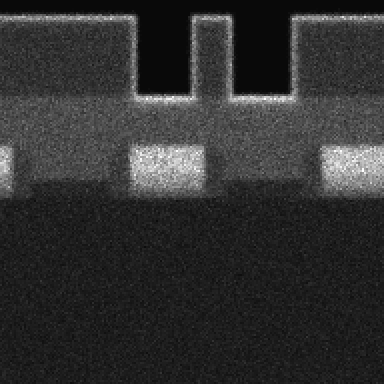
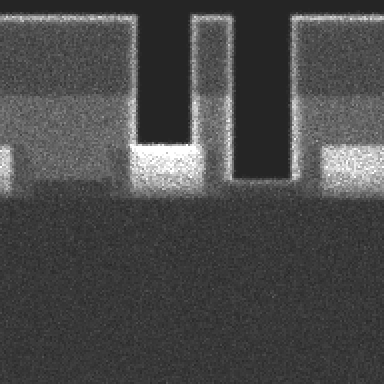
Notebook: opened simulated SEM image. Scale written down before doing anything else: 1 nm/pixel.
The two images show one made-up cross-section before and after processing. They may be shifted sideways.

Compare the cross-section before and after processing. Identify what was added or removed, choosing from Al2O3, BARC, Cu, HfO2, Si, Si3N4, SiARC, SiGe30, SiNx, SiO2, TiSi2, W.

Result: SiO2 removed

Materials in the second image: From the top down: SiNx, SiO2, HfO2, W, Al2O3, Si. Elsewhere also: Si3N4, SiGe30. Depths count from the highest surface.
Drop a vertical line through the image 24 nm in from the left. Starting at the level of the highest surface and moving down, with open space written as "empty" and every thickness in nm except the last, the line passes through SiNx 80, SiO2 54, Si3N4 48, Si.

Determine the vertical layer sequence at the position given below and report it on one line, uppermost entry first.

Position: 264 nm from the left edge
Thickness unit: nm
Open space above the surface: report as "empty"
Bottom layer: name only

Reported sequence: empty 164, SiGe30 18, Si